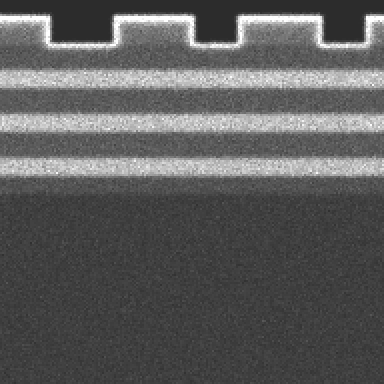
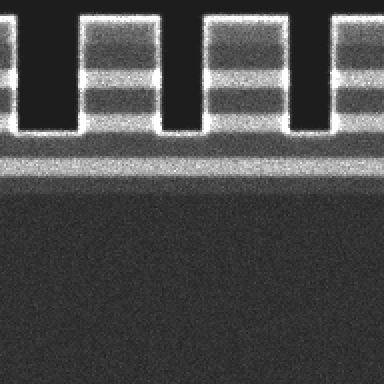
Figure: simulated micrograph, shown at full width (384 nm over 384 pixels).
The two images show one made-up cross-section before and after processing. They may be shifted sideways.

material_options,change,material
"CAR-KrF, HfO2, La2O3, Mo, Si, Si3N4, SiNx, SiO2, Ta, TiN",removed,HfO2 and Si3N4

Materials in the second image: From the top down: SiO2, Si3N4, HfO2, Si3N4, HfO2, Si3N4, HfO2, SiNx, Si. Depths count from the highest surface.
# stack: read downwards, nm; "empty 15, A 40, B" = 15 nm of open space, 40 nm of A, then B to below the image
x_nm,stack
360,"SiO2 28, Si3N4 26, HfO2 18, Si3N4 26, HfO2 18, Si3N4 26, HfO2 18, SiNx 18, Si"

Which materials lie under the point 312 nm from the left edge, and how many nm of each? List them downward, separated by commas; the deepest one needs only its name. empty 116, Si3N4 26, HfO2 18, SiNx 18, Si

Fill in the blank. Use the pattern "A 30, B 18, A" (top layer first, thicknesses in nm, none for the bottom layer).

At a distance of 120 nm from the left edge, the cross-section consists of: SiO2 28, Si3N4 26, HfO2 18, Si3N4 26, HfO2 18, Si3N4 26, HfO2 18, SiNx 18, Si